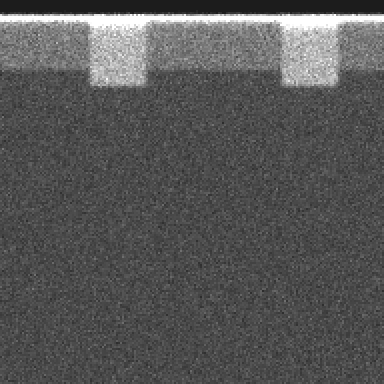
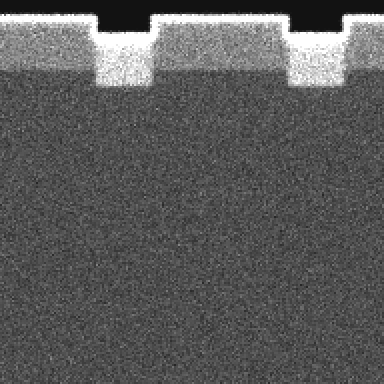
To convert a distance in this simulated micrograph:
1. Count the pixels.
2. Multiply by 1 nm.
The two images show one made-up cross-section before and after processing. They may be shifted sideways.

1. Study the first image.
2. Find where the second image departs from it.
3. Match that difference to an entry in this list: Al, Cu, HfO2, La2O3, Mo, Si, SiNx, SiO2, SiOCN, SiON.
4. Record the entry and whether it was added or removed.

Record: SiO2 / removed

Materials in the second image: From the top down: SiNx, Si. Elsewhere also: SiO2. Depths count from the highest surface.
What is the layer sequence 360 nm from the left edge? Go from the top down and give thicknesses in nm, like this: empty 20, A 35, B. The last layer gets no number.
SiNx 54, Si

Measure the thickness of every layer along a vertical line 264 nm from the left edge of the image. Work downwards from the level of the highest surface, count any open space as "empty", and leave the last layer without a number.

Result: SiNx 54, Si